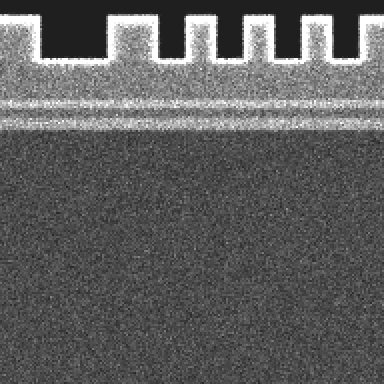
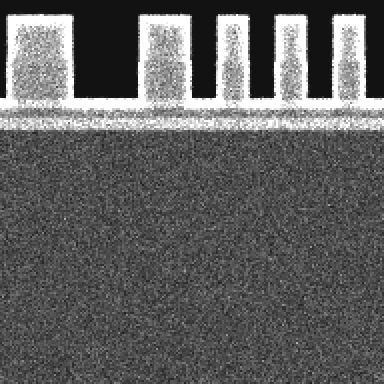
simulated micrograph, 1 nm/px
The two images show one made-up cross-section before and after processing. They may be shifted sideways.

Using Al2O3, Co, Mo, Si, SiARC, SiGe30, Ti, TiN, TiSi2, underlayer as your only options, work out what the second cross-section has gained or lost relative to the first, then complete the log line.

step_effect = removed TiN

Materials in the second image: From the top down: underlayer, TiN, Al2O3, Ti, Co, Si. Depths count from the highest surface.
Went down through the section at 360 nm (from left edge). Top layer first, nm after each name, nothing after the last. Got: underlayer 44, TiN 40, Al2O3 8, Ti 10, Co 12, Si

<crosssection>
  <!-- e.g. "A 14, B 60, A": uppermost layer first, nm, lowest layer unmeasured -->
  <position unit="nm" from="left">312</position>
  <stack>empty 84, Al2O3 8, Ti 10, Co 12, Si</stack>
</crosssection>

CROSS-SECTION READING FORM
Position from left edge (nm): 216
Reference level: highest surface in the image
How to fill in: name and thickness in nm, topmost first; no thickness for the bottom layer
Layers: empty 84, Al2O3 8, Ti 10, Co 12, Si